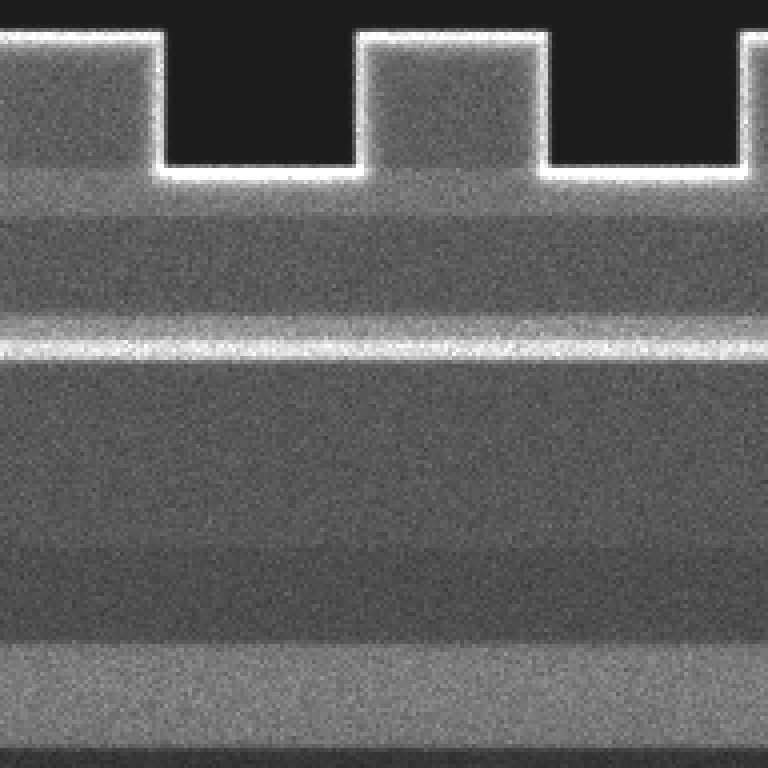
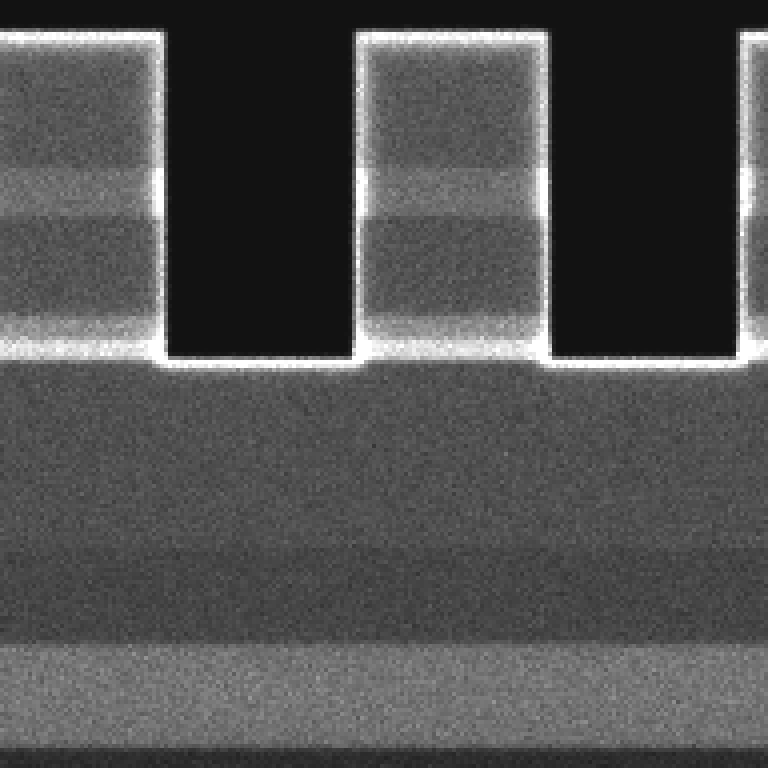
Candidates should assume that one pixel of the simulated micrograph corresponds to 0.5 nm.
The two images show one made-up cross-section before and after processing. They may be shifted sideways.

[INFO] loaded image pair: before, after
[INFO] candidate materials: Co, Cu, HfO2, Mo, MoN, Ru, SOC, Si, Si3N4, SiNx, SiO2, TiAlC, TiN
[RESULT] removed HfO2 and Ru and SiO2 and TiN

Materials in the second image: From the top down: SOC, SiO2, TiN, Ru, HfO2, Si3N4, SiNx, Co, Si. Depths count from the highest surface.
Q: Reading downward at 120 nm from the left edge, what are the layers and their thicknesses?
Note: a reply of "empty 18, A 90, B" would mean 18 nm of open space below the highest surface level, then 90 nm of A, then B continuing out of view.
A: empty 164, Si3N4 94, SiNx 48, Co 52, Si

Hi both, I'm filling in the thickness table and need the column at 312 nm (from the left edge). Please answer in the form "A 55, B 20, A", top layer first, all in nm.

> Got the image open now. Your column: empty 164, Si3N4 94, SiNx 48, Co 52, Si